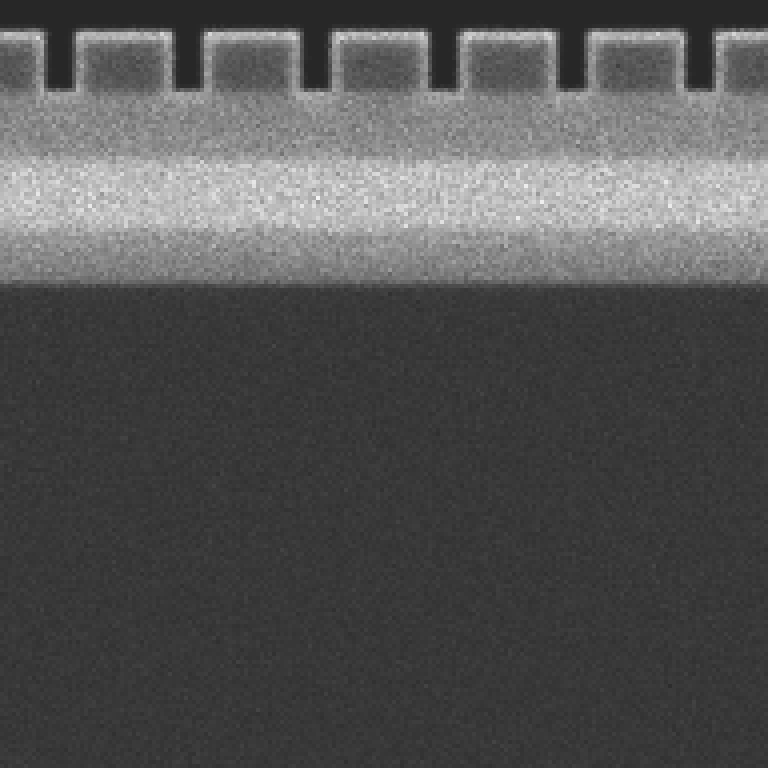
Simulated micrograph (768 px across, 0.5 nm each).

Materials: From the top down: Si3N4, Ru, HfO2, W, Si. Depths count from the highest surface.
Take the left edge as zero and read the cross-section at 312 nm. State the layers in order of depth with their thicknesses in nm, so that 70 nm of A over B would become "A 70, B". Si3N4 30, Ru 34, HfO2 34, W 28, Si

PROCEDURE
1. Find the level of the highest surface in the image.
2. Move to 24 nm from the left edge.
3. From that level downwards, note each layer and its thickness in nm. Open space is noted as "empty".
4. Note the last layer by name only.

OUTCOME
empty 30, Ru 34, HfO2 34, W 28, Si